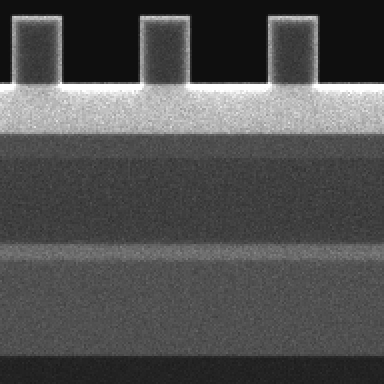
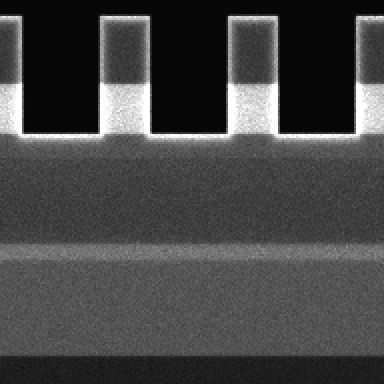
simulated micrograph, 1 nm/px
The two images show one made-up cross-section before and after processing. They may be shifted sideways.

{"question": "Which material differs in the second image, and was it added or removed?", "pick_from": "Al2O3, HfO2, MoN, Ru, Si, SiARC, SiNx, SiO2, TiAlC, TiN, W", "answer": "HfO2, removed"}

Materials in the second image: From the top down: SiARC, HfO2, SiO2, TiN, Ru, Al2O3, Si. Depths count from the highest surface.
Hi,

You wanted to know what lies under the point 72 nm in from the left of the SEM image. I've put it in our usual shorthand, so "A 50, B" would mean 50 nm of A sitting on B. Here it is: empty 118, SiO2 24, TiN 86, Ru 16, Al2O3 96, Si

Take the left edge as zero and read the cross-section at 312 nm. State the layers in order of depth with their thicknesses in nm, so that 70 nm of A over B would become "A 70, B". empty 118, SiO2 24, TiN 86, Ru 16, Al2O3 96, Si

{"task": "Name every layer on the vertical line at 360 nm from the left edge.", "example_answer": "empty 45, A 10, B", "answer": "SiARC 68, HfO2 50, SiO2 24, TiN 86, Ru 16, Al2O3 96, Si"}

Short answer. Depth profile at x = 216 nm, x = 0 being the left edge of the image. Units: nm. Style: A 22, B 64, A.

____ empty 118, SiO2 24, TiN 86, Ru 16, Al2O3 96, Si